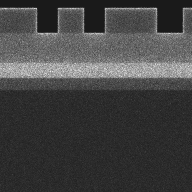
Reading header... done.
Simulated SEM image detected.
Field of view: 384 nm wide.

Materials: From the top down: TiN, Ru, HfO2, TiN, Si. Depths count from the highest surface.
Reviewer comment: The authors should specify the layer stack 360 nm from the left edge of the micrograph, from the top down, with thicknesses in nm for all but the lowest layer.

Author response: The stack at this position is empty 50, Ru 60, HfO2 30, TiN 24, Si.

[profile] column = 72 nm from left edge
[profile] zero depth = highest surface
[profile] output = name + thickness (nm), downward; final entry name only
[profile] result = TiN 50, Ru 60, HfO2 30, TiN 24, Si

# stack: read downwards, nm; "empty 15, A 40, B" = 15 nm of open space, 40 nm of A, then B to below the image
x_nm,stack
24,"TiN 50, Ru 60, HfO2 30, TiN 24, Si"